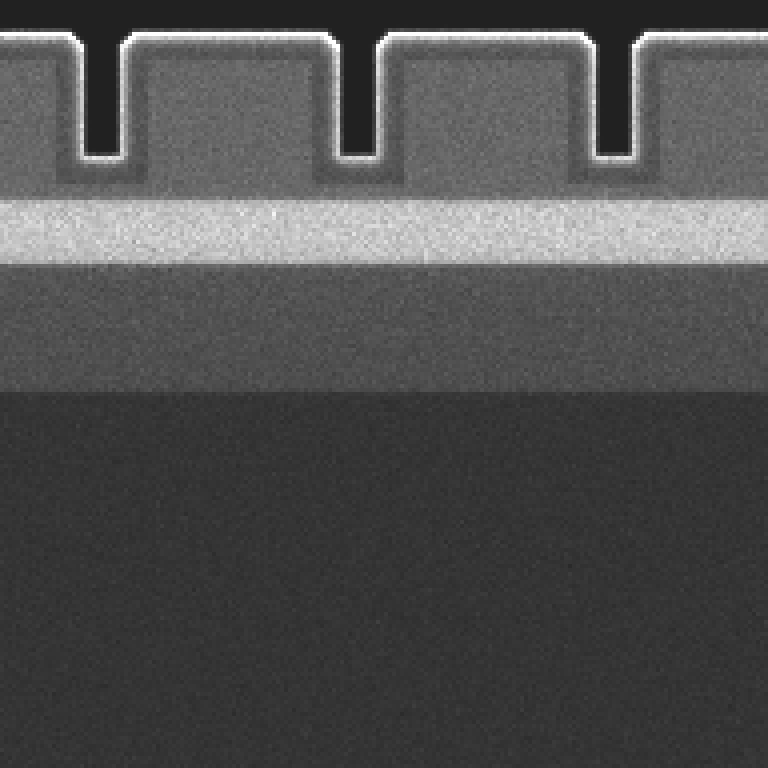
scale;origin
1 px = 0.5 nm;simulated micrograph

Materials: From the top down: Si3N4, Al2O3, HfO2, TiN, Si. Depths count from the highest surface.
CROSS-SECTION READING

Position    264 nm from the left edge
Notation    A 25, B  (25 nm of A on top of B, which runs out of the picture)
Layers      Si3N4 14, Al2O3 70, HfO2 32, TiN 64, Si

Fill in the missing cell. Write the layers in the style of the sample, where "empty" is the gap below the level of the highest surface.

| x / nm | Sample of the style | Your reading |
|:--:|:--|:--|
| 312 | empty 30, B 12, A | empty 62, Si3N4 14, Al2O3 8, HfO2 32, TiN 64, Si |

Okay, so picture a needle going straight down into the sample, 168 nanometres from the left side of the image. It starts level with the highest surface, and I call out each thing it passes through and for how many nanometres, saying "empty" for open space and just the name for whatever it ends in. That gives empty 6, Si3N4 70, Al2O3 8, HfO2 32, TiN 64, Si